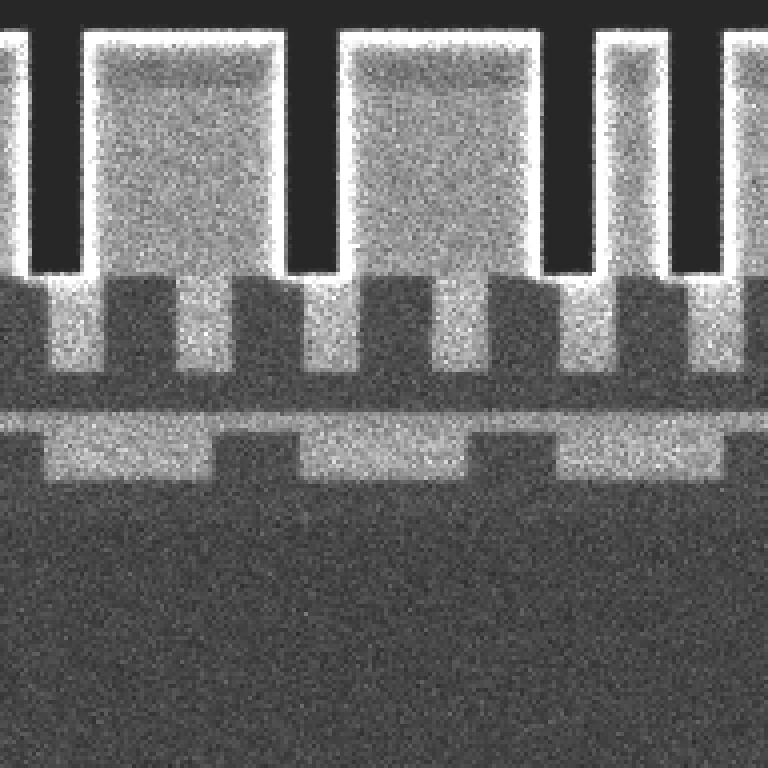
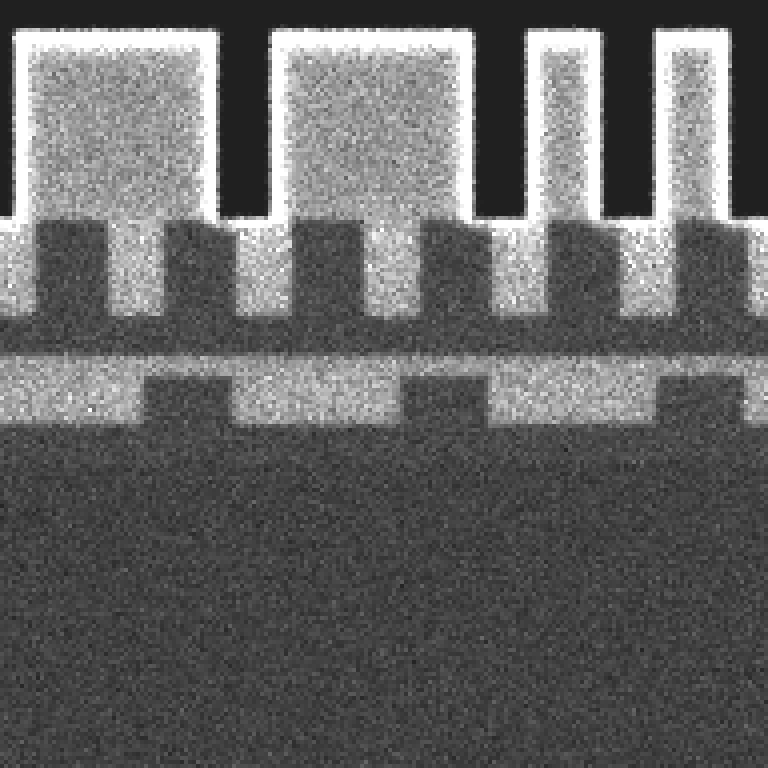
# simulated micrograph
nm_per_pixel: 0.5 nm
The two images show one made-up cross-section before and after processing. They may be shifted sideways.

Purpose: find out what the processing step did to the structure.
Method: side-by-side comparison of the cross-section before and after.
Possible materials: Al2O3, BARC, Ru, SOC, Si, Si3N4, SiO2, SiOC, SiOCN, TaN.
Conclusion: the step removed SOC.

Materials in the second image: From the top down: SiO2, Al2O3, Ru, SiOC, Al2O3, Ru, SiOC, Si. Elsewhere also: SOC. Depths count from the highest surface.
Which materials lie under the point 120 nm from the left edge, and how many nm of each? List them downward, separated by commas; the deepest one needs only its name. empty 94, Ru 48, SiOC 20, Al2O3 10, Ru 24, SiOC 20, Si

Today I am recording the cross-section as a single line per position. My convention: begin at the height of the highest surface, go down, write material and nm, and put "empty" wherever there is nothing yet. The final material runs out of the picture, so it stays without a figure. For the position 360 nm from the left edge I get SiO2 82, Al2O3 12, SiOC 68, Al2O3 10, SiOC 44, Si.